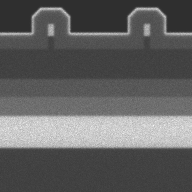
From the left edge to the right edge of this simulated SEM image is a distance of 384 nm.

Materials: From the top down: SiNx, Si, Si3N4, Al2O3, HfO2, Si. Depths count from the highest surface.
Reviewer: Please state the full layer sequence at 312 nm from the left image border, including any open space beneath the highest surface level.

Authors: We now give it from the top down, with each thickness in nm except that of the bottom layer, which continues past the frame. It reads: SiNx 82, Si 60, Si3N4 36, Al2O3 38, HfO2 64, Si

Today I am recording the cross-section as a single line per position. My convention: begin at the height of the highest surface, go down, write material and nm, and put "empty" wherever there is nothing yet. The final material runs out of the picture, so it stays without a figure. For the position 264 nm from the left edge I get empty 8, SiNx 74, Si 60, Si3N4 36, Al2O3 38, HfO2 64, Si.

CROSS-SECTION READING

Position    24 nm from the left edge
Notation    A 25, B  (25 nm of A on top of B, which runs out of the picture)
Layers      empty 50, SiNx 32, Si 60, Si3N4 36, Al2O3 38, HfO2 64, Si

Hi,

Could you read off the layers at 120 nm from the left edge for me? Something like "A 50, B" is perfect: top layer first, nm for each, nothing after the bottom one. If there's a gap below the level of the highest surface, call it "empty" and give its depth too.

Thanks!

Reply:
SiNx 82, Si 60, Si3N4 36, Al2O3 38, HfO2 64, Si